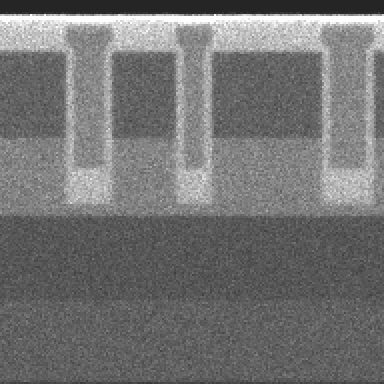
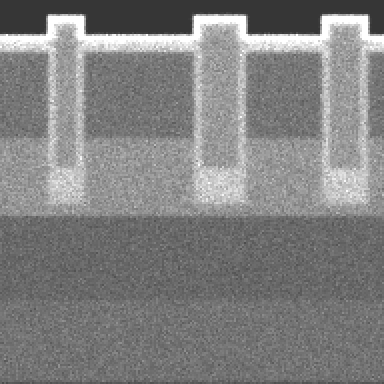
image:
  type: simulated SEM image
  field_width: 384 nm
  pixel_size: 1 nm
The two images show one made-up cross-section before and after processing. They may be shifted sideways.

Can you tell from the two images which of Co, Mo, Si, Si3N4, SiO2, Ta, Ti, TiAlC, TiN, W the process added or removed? Yes, it removed W.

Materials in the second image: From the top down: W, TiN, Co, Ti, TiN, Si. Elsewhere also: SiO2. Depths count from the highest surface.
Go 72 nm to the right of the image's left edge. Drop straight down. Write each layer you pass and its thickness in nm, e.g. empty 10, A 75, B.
SiO2 152, W 36, Co 12, Ti 84, TiN 82, Si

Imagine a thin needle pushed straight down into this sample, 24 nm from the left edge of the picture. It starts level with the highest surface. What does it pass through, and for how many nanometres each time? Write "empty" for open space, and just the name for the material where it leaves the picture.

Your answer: empty 20, W 16, TiN 86, Co 78, Ti 84, TiN 82, Si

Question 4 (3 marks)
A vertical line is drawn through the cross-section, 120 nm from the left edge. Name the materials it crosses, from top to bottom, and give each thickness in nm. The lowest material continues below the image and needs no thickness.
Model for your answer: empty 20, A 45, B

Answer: empty 20, W 16, TiN 86, Co 78, Ti 84, TiN 82, Si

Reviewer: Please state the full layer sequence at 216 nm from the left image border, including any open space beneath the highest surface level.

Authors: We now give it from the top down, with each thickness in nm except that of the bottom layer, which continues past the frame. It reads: SiO2 152, W 36, Co 12, Ti 84, TiN 82, Si